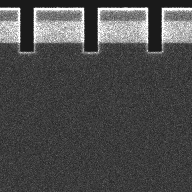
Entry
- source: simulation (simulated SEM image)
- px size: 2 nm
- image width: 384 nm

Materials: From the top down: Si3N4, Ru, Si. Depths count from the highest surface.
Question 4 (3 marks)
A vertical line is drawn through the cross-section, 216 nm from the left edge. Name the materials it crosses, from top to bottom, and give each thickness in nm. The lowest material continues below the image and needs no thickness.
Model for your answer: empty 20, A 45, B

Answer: Si3N4 26, Ru 44, Si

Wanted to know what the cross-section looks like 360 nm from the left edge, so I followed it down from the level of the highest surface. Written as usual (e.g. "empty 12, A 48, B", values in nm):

Si3N4 26, Ru 44, Si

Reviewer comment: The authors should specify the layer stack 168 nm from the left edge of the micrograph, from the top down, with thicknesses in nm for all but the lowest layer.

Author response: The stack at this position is empty 88, Si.